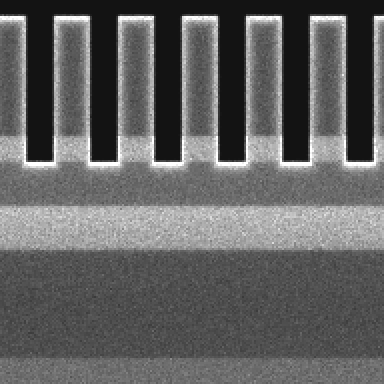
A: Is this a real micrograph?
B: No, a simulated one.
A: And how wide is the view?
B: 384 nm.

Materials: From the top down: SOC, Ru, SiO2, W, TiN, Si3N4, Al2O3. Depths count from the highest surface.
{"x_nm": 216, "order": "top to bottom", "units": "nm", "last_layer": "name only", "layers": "SOC 120, Ru 26, SiO2 44, W 44, TiN 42, Si3N4 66, Al2O3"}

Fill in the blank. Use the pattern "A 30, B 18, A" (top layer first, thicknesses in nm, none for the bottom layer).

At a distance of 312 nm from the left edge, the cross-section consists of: SOC 120, Ru 26, SiO2 44, W 44, TiN 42, Si3N4 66, Al2O3